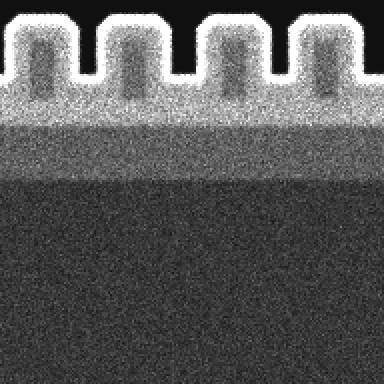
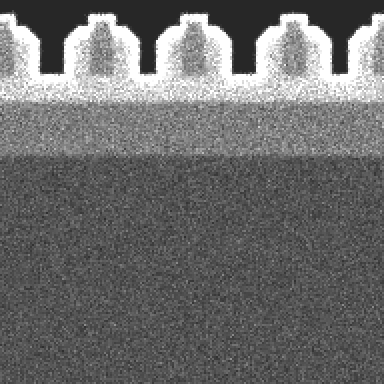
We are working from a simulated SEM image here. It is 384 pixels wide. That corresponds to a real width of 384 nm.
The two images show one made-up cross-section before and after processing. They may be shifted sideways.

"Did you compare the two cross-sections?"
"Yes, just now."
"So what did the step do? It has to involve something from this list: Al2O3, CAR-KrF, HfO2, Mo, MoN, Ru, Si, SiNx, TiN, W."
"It removed Al2O3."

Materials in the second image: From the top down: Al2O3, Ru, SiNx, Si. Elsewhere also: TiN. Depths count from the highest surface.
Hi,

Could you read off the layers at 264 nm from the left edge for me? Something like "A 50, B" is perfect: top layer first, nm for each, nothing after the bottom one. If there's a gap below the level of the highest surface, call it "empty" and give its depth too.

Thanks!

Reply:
empty 18, Al2O3 42, Ru 26, SiNx 54, Si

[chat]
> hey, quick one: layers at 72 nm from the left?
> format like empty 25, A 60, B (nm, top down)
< empty 18, Al2O3 42, Ru 26, SiNx 54, Si